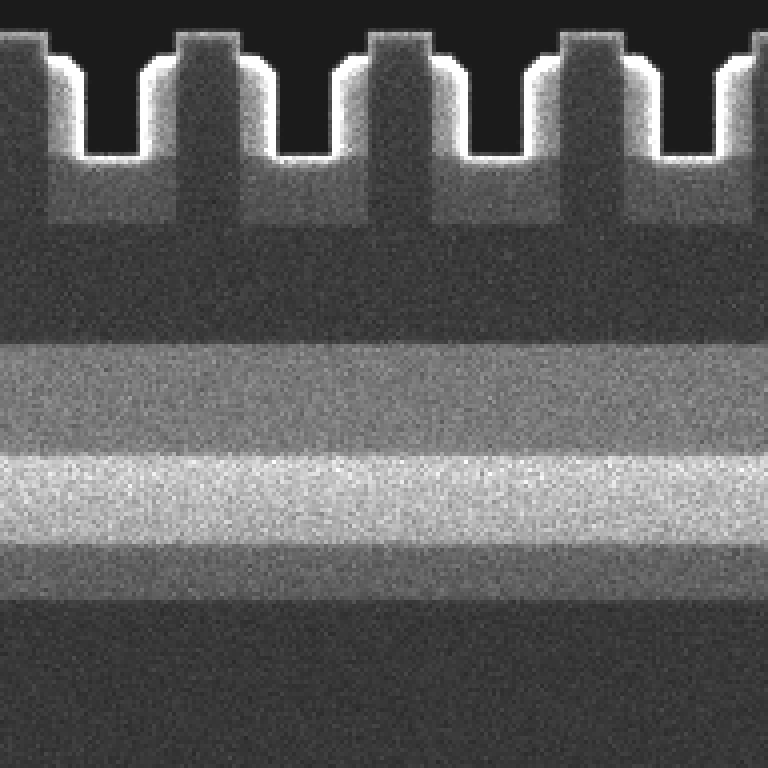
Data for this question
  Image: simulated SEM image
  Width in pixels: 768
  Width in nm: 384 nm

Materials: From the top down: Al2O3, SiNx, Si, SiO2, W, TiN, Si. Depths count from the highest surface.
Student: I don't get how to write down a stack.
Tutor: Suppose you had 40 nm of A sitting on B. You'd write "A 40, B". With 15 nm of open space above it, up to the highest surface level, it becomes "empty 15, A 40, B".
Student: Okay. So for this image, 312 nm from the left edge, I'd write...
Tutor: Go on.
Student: empty 12, Al2O3 50, SiNx 34, Si 60, SiO2 56, W 44, TiN 28, Si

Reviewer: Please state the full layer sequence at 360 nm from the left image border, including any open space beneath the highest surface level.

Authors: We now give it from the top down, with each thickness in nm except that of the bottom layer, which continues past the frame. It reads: empty 18, Al2O3 44, SiNx 34, Si 60, SiO2 56, W 44, TiN 28, Si